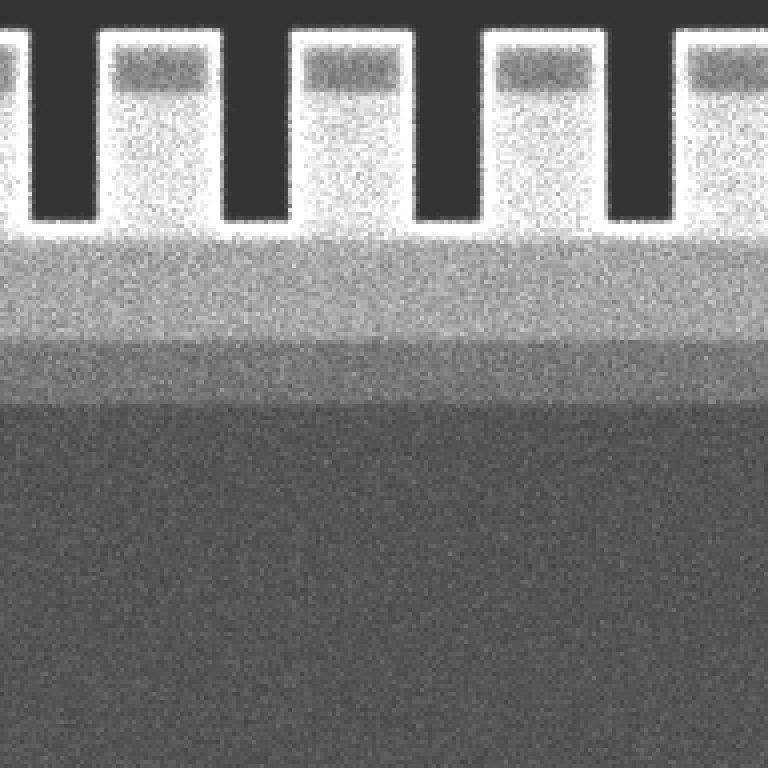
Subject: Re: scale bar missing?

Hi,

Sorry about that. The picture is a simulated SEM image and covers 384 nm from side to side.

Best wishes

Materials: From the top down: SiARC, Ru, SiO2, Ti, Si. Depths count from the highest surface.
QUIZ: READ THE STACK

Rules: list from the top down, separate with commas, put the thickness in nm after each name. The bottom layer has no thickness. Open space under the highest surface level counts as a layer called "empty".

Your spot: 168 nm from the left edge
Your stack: SiARC 30, Ru 74, SiO2 50, Ti 32, Si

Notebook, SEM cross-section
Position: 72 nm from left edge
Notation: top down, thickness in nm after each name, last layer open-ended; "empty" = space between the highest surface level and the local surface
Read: SiARC 30, Ru 74, SiO2 50, Ti 32, Si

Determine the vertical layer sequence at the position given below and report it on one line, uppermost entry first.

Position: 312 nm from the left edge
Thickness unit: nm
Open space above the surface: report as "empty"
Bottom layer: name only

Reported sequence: empty 96, Ru 8, SiO2 50, Ti 32, Si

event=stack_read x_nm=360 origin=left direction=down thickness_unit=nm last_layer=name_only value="SiARC 30, Ru 74, SiO2 50, Ti 32, Si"